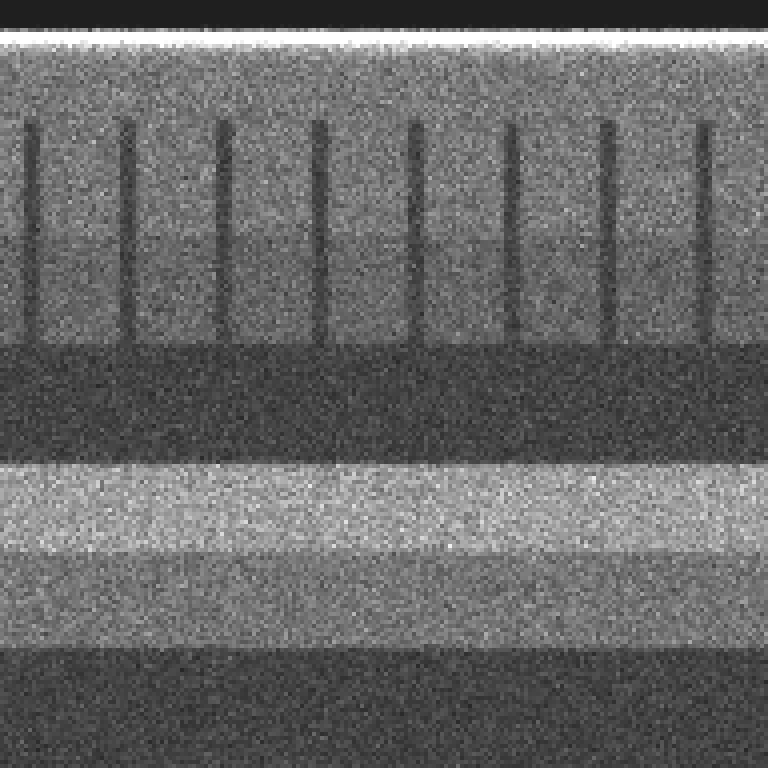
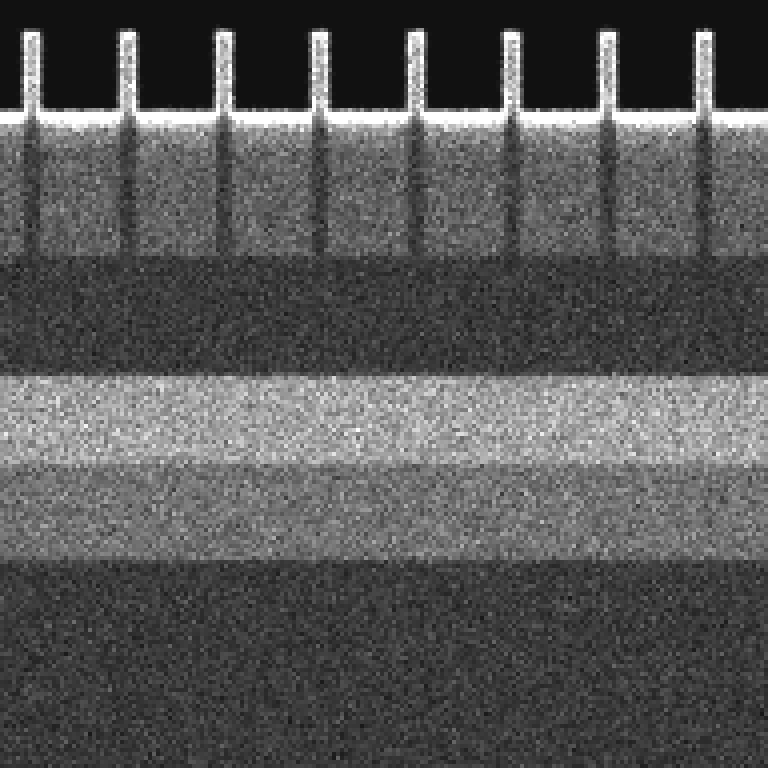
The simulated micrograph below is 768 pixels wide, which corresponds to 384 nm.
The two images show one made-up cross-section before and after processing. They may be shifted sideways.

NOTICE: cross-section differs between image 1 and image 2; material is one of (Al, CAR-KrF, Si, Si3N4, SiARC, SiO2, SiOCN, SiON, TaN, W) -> removed: SiARC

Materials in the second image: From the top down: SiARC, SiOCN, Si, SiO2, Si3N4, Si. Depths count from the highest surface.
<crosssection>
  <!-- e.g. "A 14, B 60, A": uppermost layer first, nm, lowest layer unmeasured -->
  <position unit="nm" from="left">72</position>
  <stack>empty 40, SiARC 18, SiOCN 54, Si 60, SiO2 44, Si3N4 48, Si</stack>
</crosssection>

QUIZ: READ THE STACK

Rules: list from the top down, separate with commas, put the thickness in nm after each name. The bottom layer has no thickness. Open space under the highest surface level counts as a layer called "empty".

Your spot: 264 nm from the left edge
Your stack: empty 40, SiARC 18, SiOCN 54, Si 60, SiO2 44, Si3N4 48, Si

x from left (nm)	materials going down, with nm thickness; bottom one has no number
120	empty 40, SiARC 18, SiOCN 54, Si 60, SiO2 44, Si3N4 48, Si